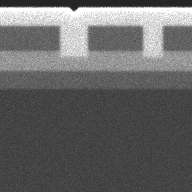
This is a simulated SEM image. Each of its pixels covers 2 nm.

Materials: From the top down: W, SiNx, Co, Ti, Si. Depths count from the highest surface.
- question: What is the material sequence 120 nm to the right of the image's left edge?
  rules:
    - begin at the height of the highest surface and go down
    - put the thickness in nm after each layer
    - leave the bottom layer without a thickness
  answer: W 98, Co 28, Ti 36, Si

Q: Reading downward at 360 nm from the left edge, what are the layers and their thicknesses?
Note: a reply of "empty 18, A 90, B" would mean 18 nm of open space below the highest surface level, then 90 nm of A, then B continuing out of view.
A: W 36, SiNx 50, Co 40, Ti 36, Si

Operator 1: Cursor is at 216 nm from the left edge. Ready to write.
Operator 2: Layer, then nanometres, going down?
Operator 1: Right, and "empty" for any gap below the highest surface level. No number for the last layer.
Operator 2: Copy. W 36, SiNx 50, Co 40, Ti 36, Si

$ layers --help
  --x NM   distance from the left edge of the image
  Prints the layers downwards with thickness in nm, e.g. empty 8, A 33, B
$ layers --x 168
W 98, Co 28, Ti 36, Si